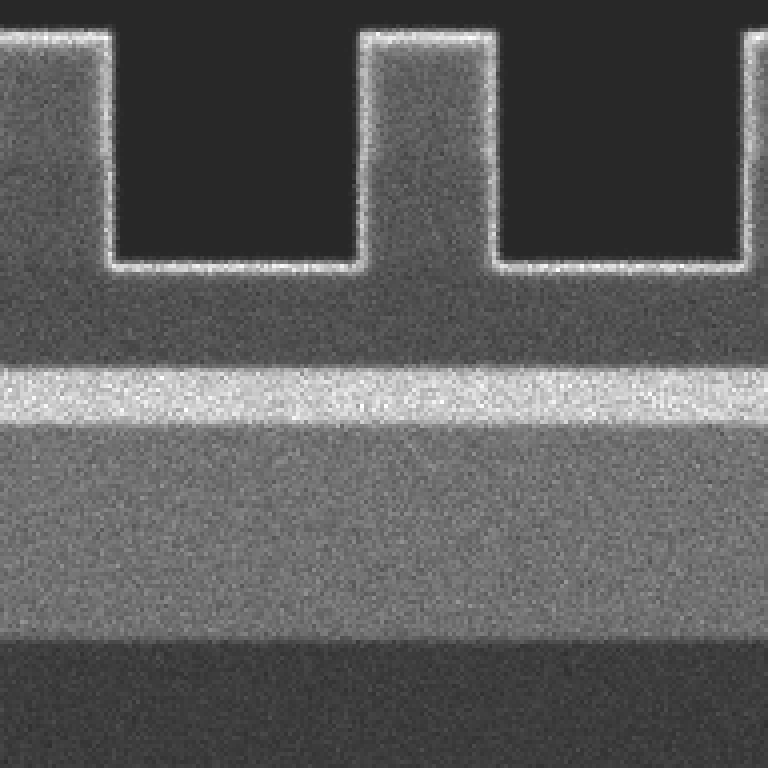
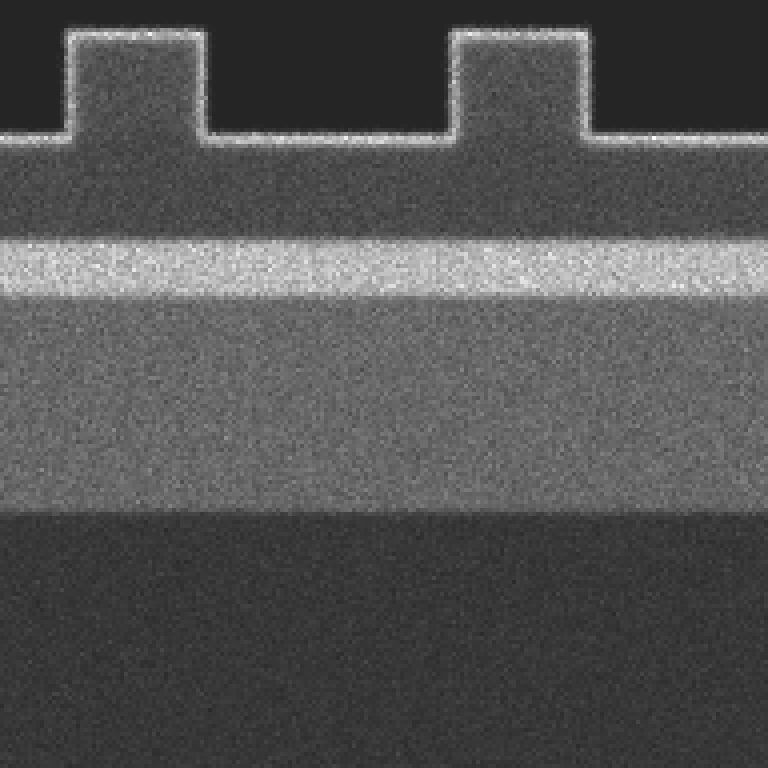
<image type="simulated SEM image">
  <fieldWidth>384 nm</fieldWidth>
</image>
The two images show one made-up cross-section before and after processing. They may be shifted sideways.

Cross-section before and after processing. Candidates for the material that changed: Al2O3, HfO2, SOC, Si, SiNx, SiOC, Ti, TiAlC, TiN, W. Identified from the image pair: SOC (removed).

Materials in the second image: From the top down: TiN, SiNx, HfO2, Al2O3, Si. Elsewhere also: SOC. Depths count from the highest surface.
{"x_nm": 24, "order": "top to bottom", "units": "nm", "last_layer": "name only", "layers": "empty 52, SiNx 52, HfO2 28, Al2O3 108, Si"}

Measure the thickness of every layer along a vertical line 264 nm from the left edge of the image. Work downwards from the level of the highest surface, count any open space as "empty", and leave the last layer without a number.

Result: TiN 52, SiNx 52, HfO2 28, Al2O3 108, Si